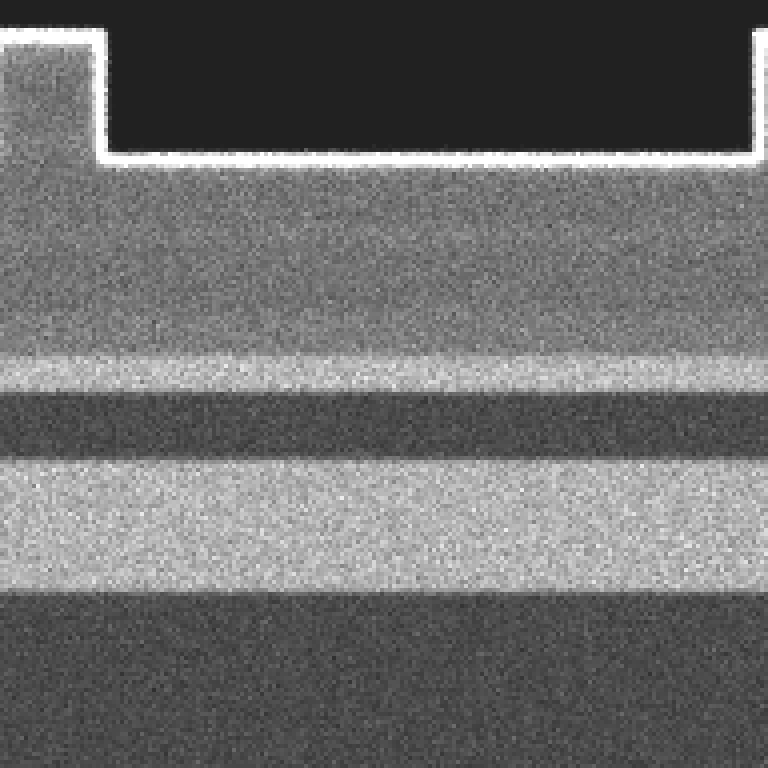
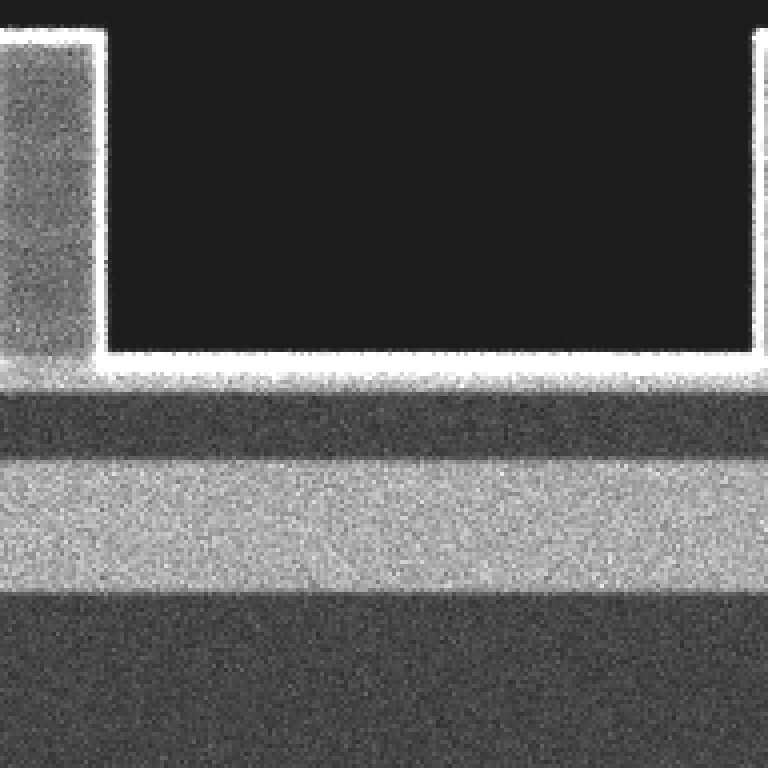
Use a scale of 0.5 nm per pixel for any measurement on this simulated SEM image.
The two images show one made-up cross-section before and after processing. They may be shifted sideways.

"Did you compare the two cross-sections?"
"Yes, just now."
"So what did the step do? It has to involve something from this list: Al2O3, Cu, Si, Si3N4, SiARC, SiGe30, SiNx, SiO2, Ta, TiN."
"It removed SiNx and TiN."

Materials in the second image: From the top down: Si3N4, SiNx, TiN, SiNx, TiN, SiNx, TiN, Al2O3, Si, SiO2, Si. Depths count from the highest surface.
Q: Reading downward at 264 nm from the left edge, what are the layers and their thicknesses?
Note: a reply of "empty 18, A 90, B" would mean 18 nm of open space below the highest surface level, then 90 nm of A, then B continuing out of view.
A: empty 162, Al2O3 18, Si 34, SiO2 66, Si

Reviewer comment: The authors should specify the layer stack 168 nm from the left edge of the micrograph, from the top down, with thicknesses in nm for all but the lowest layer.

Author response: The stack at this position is empty 162, Al2O3 18, Si 34, SiO2 66, Si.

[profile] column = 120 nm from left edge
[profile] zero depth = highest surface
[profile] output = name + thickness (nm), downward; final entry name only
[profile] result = empty 162, Al2O3 18, Si 34, SiO2 66, Si